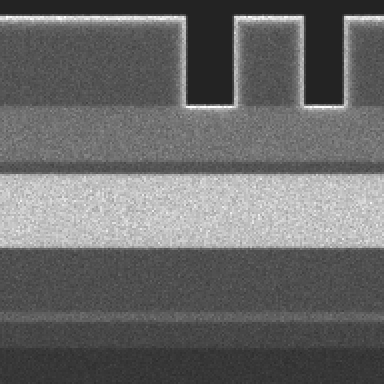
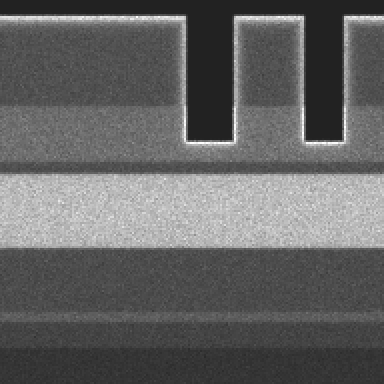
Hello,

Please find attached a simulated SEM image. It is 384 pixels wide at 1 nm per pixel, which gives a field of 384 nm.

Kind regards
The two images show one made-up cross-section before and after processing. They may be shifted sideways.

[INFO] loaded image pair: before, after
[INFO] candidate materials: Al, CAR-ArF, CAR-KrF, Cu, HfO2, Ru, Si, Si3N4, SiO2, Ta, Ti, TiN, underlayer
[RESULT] removed Ru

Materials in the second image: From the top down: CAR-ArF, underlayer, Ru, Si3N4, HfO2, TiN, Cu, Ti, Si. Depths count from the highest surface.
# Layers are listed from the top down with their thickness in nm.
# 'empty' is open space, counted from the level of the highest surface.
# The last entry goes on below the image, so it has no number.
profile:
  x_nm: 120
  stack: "CAR-ArF 62, underlayer 28, Ru 56, Si3N4 12, HfO2 74, TiN 64, Cu 10, Ti 26, Si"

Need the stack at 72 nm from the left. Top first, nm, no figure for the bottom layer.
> CAR-ArF 62, underlayer 28, Ru 56, Si3N4 12, HfO2 74, TiN 64, Cu 10, Ti 26, Si